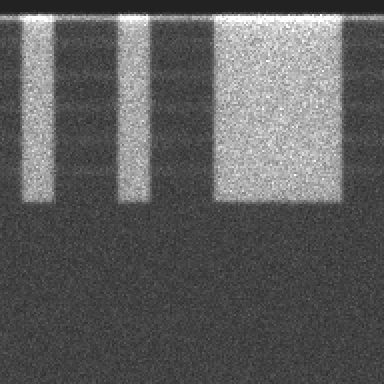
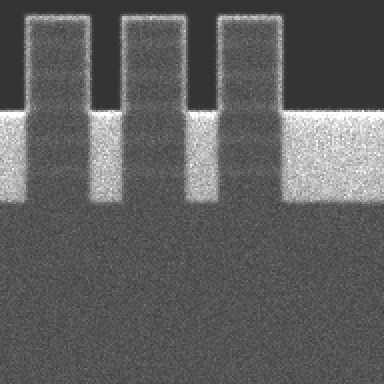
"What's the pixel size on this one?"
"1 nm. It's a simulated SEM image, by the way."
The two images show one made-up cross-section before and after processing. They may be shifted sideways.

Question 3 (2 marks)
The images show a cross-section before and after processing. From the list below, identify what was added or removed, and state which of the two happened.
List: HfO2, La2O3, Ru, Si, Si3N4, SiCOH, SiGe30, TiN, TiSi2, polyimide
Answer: Ru was removed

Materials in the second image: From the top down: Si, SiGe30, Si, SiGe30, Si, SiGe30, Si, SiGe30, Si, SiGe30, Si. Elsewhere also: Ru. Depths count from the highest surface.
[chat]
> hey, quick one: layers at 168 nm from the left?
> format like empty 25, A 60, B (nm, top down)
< Si 22, SiGe30 10, Si 22, SiGe30 10, Si 22, SiGe30 10, Si 22, SiGe30 10, Si 22, SiGe30 10, Si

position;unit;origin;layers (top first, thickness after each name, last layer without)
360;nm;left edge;empty 96, Ru 90, Si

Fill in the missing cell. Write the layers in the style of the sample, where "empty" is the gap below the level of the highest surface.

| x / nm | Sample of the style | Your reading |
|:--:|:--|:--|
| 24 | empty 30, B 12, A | empty 96, Ru 90, Si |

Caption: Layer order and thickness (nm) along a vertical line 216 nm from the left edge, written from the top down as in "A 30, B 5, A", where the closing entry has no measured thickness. empty 96, Ru 90, Si